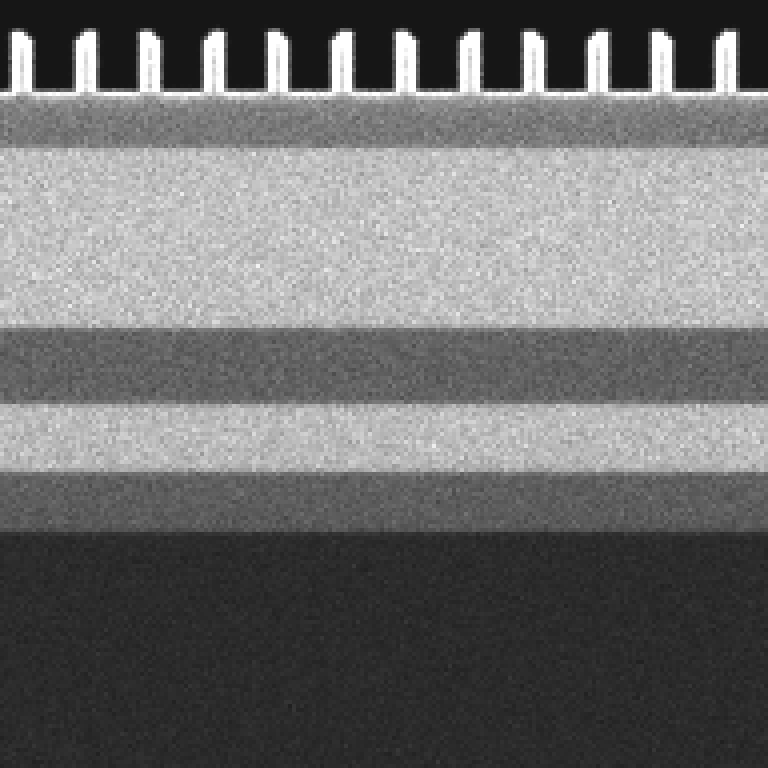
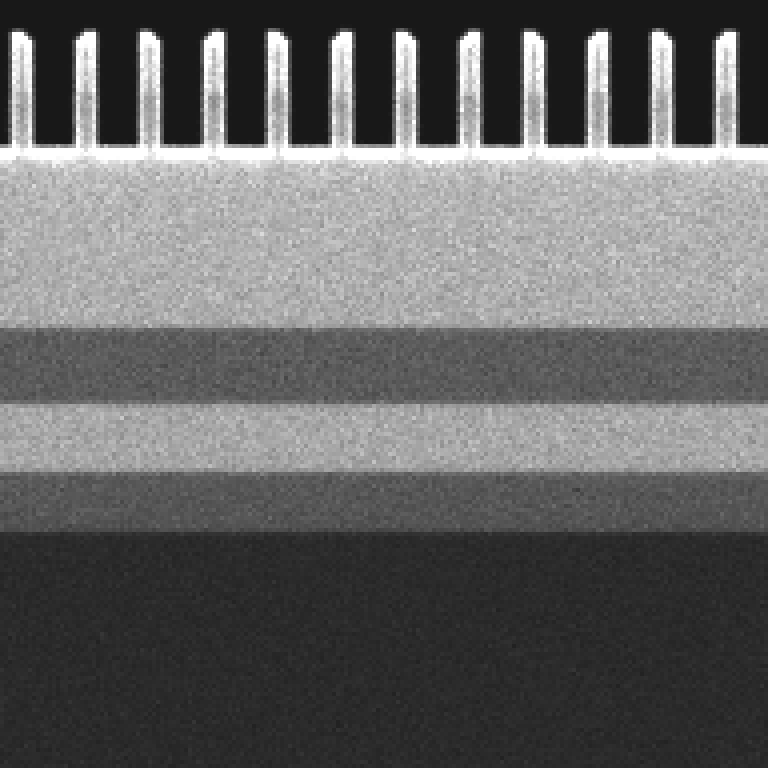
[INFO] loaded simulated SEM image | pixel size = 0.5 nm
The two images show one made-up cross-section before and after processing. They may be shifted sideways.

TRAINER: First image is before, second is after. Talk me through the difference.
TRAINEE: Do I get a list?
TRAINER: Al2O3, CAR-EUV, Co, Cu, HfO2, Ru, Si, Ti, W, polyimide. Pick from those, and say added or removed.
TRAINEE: removed: Ru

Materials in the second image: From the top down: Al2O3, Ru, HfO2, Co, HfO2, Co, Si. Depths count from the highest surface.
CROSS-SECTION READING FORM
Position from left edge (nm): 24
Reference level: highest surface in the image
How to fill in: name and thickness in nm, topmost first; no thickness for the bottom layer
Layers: empty 58, HfO2 90, Co 38, HfO2 34, Co 30, Si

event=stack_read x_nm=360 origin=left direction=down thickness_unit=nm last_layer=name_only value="empty 2, Al2O3 28, Ru 28, HfO2 90, Co 38, HfO2 34, Co 30, Si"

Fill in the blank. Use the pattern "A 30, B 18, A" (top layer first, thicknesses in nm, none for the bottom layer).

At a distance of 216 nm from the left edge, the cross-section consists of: empty 58, HfO2 90, Co 38, HfO2 34, Co 30, Si